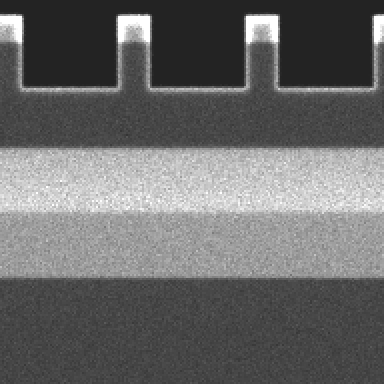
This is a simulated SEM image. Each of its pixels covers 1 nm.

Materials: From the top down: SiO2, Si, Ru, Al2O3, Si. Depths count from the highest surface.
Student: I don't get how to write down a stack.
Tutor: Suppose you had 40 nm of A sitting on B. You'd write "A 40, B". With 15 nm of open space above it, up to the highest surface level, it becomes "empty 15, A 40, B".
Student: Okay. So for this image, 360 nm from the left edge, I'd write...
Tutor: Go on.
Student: empty 72, Si 60, Ru 64, Al2O3 66, Si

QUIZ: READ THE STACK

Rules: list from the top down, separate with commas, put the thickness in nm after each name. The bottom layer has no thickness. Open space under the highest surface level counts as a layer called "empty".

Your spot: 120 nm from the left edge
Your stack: SiO2 26, Si 106, Ru 64, Al2O3 66, Si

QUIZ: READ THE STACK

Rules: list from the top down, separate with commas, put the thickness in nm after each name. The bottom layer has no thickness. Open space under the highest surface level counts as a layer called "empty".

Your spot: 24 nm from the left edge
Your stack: empty 72, Si 60, Ru 64, Al2O3 66, Si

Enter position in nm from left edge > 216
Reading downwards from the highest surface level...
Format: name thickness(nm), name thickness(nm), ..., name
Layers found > empty 72, Si 60, Ru 64, Al2O3 66, Si